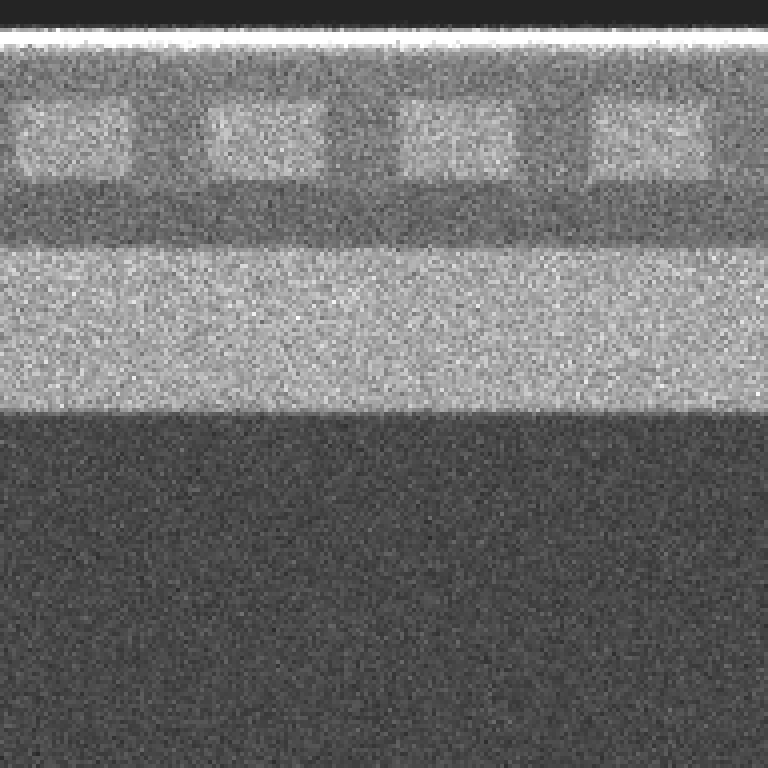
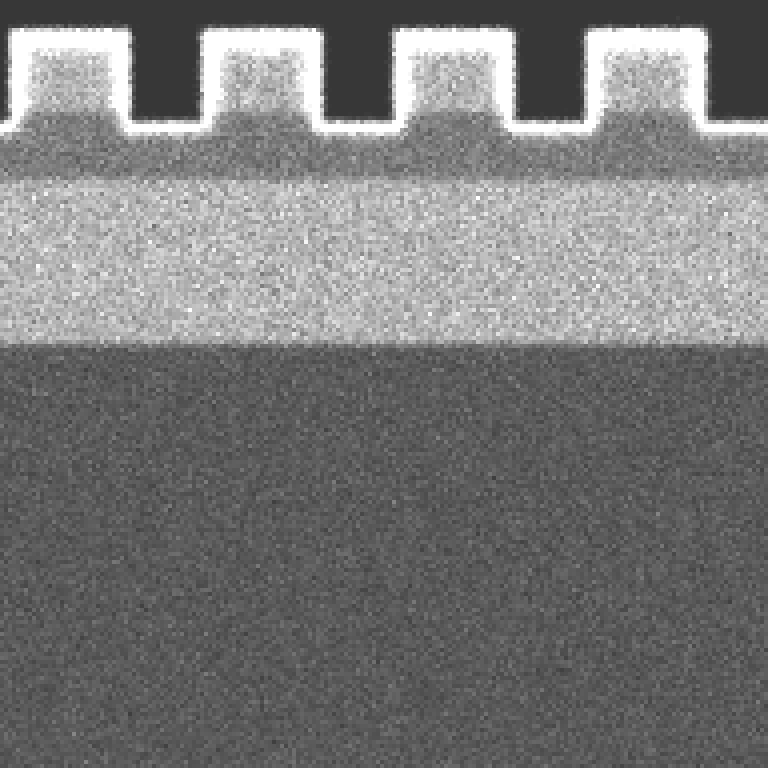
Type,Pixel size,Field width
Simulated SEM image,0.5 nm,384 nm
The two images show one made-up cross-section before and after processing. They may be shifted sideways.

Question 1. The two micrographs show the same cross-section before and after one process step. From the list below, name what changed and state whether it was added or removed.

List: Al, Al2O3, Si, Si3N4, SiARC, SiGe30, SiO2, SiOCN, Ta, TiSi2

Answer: SiARC, removed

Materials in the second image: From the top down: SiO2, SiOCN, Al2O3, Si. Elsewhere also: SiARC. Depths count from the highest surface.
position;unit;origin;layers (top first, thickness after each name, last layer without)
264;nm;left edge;empty 46, SiOCN 28, Al2O3 82, Si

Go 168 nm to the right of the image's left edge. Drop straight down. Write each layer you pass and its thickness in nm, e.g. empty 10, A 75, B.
empty 46, SiOCN 28, Al2O3 82, Si